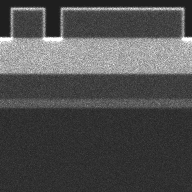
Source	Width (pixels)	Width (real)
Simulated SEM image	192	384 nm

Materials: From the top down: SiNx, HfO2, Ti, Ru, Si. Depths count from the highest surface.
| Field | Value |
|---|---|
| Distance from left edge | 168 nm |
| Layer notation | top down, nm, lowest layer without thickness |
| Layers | SiNx 60, HfO2 72, Ti 50, Ru 18, Si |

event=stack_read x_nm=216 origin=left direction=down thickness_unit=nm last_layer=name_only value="SiNx 60, HfO2 72, Ti 50, Ru 18, Si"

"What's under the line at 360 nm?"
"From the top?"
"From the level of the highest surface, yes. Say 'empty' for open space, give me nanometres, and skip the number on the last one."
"SiNx 60, HfO2 72, Ti 50, Ru 18, Si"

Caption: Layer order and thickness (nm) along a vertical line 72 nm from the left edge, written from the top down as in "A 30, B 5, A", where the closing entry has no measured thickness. SiNx 60, HfO2 72, Ti 50, Ru 18, Si